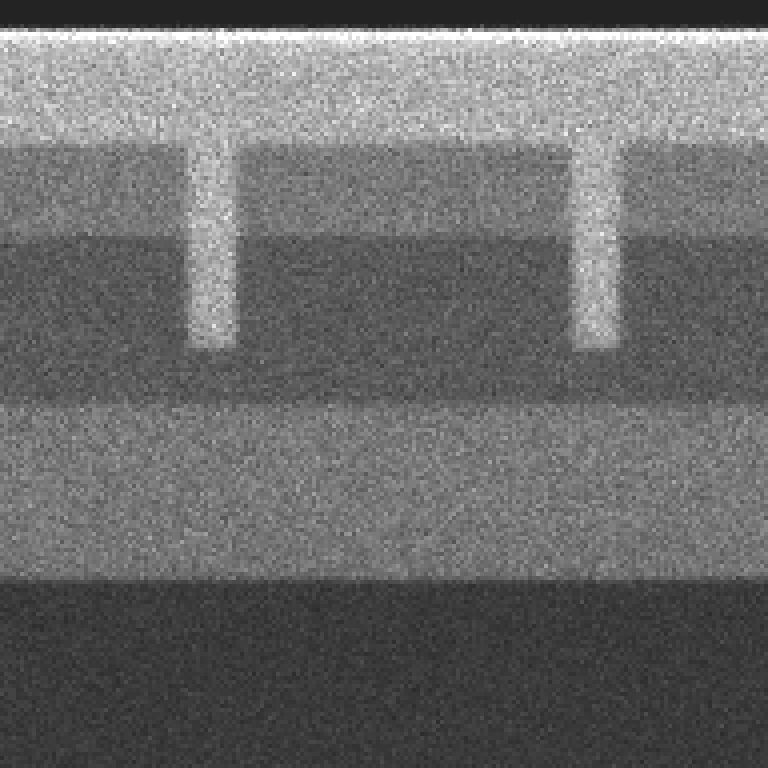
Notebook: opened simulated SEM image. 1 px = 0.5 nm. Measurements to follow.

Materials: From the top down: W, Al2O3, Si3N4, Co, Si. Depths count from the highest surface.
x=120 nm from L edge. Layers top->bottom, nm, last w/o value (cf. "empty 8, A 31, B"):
W 56, Al2O3 46, Si3N4 84, Co 88, Si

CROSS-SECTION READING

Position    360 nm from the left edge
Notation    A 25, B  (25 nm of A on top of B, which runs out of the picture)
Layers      W 56, Al2O3 46, Si3N4 84, Co 88, Si